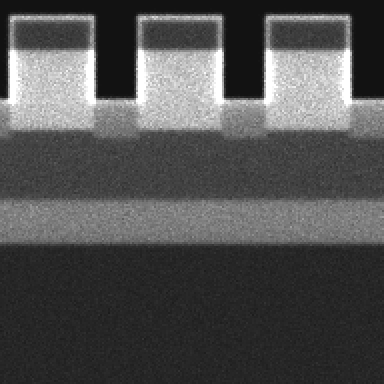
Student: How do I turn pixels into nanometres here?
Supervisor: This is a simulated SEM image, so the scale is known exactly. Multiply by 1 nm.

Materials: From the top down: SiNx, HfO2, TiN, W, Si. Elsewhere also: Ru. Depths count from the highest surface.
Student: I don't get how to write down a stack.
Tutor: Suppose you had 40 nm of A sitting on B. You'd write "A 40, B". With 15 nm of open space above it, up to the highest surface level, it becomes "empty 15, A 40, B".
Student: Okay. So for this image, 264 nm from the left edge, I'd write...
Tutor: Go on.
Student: empty 84, Ru 38, TiN 62, W 44, Si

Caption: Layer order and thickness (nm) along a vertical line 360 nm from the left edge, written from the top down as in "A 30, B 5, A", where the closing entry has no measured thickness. empty 84, Ru 38, TiN 62, W 44, Si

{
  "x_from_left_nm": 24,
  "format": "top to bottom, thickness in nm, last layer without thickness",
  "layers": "SiNx 34, HfO2 80, TiN 70, W 44, Si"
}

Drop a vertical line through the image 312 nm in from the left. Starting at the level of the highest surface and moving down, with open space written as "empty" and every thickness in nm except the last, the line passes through SiNx 34, HfO2 80, TiN 70, W 44, Si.